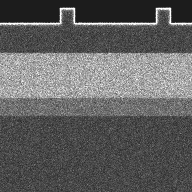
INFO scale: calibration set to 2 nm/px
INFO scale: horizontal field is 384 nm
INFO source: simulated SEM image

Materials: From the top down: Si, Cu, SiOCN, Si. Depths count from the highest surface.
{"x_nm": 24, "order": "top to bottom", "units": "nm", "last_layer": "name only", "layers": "empty 30, Si 60, Cu 90, SiOCN 36, Si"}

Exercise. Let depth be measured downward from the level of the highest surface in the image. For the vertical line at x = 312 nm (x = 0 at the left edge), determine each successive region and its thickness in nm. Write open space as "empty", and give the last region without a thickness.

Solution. Si 90, Cu 90, SiOCN 36, Si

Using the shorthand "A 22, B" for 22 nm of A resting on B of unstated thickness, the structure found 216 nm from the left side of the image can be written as empty 30, Si 60, Cu 90, SiOCN 36, Si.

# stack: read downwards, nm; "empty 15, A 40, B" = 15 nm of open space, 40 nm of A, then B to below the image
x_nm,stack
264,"empty 30, Si 60, Cu 90, SiOCN 36, Si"